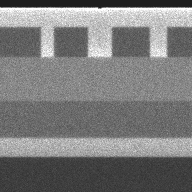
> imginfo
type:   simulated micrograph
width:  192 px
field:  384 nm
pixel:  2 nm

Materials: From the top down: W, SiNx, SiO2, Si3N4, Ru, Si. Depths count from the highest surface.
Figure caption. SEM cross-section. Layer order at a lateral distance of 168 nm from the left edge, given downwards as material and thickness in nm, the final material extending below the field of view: W 38, SiNx 60, SiO2 88, Si3N4 74, Ru 38, Si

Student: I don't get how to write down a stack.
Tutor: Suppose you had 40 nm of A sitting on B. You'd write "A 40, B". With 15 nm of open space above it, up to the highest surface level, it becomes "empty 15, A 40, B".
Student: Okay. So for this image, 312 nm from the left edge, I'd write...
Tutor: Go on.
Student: W 98, SiO2 88, Si3N4 74, Ru 38, Si